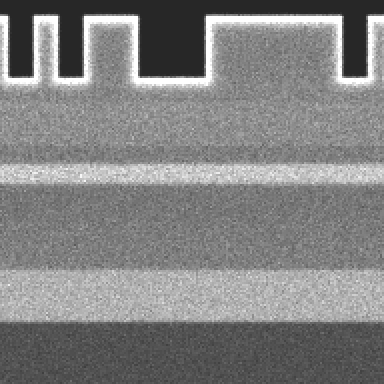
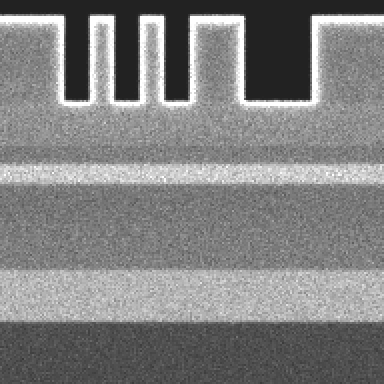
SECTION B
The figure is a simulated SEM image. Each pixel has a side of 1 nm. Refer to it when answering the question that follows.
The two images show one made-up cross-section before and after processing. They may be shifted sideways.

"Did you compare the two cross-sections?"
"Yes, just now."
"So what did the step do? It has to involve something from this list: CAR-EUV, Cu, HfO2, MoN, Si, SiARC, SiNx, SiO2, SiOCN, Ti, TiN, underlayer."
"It removed underlayer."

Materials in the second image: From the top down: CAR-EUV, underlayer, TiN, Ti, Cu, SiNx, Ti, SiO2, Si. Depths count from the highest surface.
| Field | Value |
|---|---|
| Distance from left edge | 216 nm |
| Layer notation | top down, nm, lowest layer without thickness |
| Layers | CAR-EUV 62, underlayer 24, TiN 44, Ti 18, Cu 20, SiNx 36, Ti 50, SiO2 52, Si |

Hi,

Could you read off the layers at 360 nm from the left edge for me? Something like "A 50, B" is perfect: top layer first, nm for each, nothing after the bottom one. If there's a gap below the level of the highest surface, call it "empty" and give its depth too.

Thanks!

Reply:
CAR-EUV 62, underlayer 24, TiN 44, Ti 18, Cu 20, SiNx 36, Ti 50, SiO2 52, Si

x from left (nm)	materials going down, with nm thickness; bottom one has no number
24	CAR-EUV 62, underlayer 24, TiN 44, Ti 18, Cu 20, SiNx 36, Ti 50, SiO2 52, Si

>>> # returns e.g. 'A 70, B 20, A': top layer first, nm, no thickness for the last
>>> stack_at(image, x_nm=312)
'CAR-EUV 62, underlayer 24, TiN 44, Ti 18, Cu 20, SiNx 36, Ti 50, SiO2 52, Si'